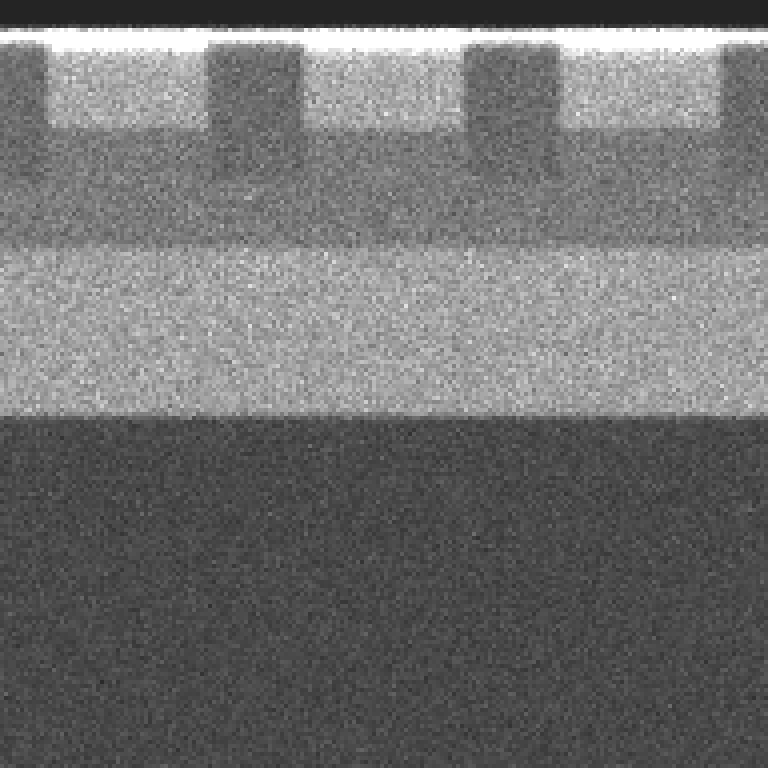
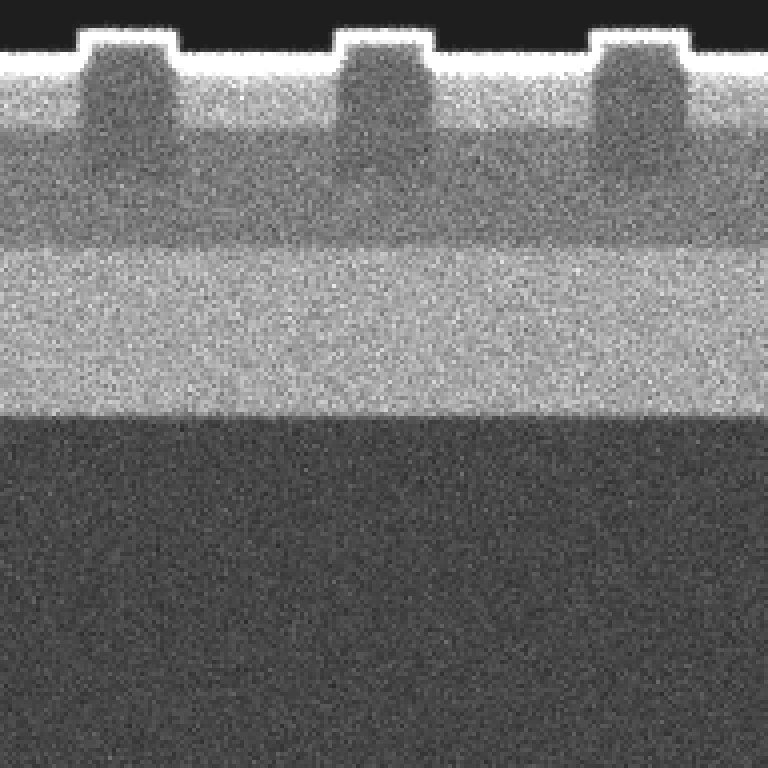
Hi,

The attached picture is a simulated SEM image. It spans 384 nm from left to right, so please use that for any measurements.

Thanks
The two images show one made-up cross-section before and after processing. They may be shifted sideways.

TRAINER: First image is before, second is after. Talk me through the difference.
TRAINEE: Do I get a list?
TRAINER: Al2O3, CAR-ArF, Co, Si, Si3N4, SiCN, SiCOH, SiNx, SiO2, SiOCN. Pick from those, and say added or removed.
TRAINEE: removed: Al2O3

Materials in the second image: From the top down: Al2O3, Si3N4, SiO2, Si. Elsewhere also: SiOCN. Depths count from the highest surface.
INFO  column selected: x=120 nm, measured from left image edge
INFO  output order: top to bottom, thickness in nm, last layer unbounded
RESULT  empty 12, Al2O3 36, Si3N4 60, SiO2 84, Si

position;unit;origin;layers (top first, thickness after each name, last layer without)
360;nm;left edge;empty 12, Al2O3 36, Si3N4 60, SiO2 84, Si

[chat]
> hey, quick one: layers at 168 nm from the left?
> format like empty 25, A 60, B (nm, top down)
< SiOCN 74, Si3N4 34, SiO2 84, Si